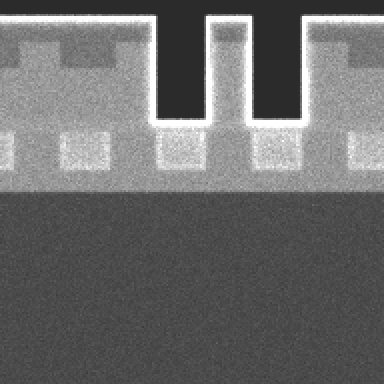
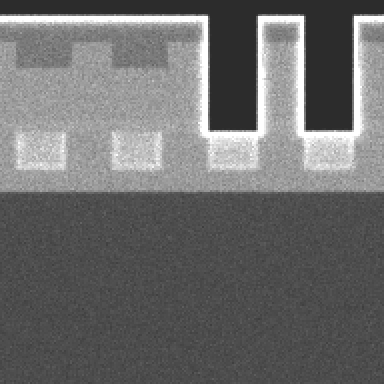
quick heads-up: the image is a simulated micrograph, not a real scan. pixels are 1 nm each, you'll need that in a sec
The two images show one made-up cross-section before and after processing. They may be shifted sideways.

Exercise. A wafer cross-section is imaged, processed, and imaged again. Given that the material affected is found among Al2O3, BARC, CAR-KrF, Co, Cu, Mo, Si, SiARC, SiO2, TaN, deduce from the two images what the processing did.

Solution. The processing removed Al2O3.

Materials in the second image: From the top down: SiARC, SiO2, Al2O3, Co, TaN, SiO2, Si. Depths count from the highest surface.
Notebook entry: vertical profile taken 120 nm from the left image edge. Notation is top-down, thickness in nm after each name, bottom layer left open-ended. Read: SiARC 52, SiO2 52, Al2O3 12, Co 32, TaN 6, SiO2 22, Si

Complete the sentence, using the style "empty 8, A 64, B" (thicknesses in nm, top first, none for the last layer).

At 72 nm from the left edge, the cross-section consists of SiARC 26, SiO2 78, Al2O3 12, SiO2 60, Si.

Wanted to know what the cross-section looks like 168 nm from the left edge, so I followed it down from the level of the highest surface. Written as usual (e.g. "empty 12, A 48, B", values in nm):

SiARC 26, SiO2 78, Al2O3 12, SiO2 60, Si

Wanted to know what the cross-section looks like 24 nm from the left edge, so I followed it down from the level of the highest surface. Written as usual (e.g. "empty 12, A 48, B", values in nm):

SiARC 52, SiO2 52, Al2O3 12, Co 32, TaN 6, SiO2 22, Si